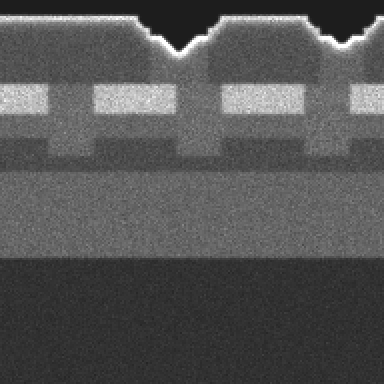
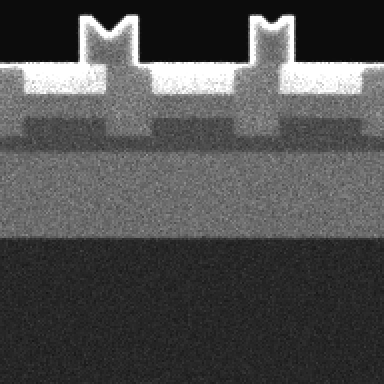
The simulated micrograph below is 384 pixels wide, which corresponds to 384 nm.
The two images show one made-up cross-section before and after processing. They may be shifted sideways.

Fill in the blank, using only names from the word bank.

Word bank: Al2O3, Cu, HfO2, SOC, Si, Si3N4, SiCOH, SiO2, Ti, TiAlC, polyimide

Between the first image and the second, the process removed SOC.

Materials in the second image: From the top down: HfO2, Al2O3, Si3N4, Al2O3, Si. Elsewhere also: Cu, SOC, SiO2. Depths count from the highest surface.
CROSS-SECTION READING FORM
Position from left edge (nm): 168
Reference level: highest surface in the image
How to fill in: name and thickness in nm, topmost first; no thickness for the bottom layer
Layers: empty 48, HfO2 30, Al2O3 24, Si3N4 34, Al2O3 86, Si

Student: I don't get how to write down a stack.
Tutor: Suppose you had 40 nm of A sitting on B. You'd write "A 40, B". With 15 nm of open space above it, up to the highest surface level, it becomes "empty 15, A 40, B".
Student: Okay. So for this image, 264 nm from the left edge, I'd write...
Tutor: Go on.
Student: empty 4, SiO2 44, Cu 72, Si3N4 16, Al2O3 86, Si